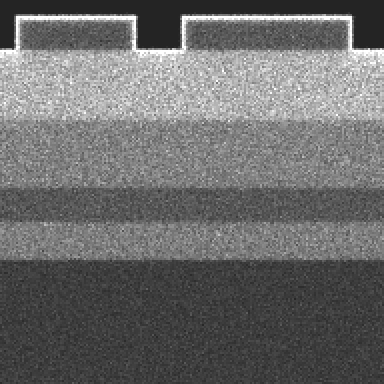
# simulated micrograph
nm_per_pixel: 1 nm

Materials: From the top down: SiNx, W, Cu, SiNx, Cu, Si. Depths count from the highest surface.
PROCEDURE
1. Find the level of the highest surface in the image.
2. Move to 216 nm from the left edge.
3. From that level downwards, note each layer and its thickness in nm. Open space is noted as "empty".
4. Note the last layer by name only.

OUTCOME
SiNx 34, W 70, Cu 68, SiNx 34, Cu 38, Si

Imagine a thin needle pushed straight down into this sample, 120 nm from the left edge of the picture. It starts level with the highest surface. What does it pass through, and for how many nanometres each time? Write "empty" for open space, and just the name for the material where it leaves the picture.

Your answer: SiNx 34, W 70, Cu 68, SiNx 34, Cu 38, Si